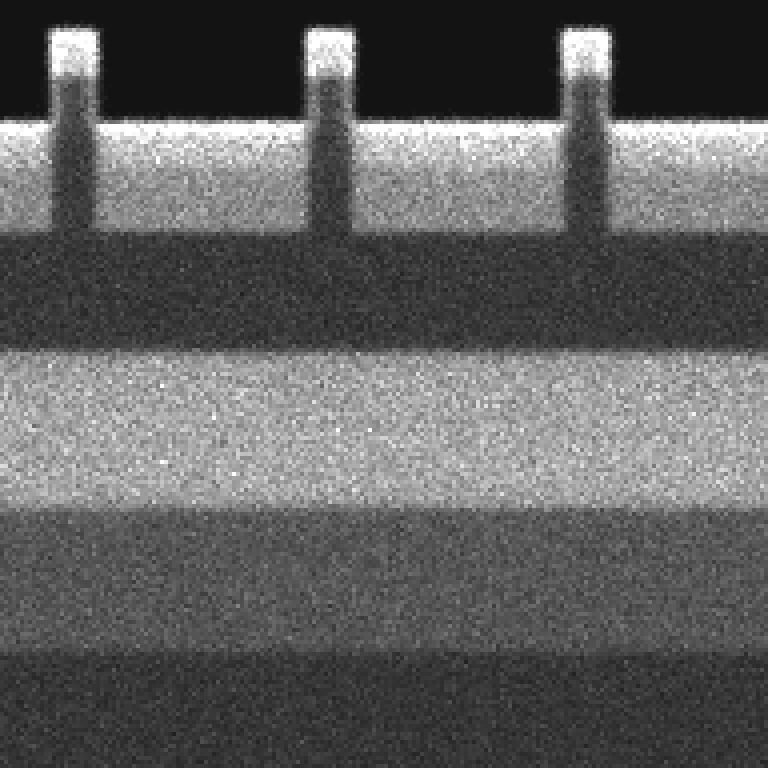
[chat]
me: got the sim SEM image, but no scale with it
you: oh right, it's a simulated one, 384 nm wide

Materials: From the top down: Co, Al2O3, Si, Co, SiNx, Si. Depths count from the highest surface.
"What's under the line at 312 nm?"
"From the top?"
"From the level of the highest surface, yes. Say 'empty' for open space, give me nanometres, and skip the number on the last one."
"empty 46, Co 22, Al2O3 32, Si 60, Co 78, SiNx 72, Si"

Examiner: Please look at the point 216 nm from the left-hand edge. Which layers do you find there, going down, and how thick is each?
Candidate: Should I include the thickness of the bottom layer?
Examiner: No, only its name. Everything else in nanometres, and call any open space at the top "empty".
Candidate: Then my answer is empty 46, Co 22, Al2O3 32, Si 60, Co 78, SiNx 72, Si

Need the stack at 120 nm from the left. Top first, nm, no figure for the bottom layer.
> empty 46, Co 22, Al2O3 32, Si 60, Co 78, SiNx 72, Si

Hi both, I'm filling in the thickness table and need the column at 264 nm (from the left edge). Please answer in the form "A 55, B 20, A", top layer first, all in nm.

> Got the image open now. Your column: empty 46, Co 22, Al2O3 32, Si 60, Co 78, SiNx 72, Si